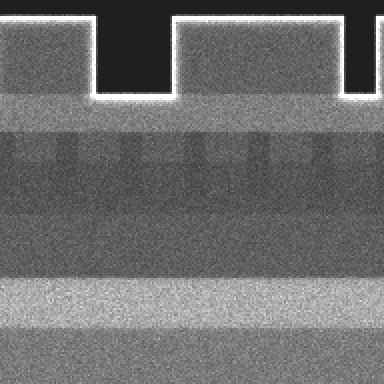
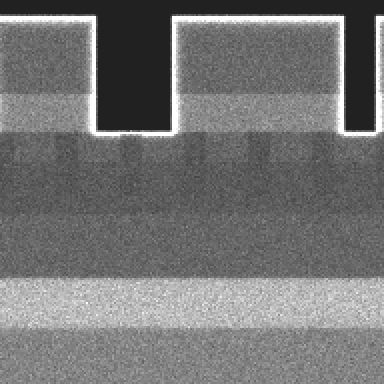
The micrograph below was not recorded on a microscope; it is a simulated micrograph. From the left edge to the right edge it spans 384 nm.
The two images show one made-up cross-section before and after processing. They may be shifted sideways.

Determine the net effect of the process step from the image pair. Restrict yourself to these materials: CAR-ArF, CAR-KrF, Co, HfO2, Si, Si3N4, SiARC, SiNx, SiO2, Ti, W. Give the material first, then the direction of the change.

SiO2: removed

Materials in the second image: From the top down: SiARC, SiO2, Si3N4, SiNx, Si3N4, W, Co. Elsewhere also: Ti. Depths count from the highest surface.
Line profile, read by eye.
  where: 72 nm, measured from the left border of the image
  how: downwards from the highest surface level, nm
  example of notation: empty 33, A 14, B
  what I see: SiARC 78, SiO2 38, Ti 64, SiNx 18, Si3N4 64, W 50, Co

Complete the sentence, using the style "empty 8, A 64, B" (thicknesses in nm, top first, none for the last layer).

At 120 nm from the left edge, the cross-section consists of empty 116, Ti 64, SiNx 18, Si3N4 64, W 50, Co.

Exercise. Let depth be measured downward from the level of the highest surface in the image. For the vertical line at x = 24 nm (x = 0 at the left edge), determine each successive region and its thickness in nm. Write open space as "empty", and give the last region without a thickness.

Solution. SiARC 78, SiO2 38, Si3N4 30, SiNx 52, Si3N4 64, W 50, Co